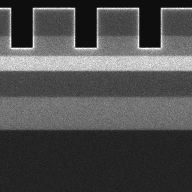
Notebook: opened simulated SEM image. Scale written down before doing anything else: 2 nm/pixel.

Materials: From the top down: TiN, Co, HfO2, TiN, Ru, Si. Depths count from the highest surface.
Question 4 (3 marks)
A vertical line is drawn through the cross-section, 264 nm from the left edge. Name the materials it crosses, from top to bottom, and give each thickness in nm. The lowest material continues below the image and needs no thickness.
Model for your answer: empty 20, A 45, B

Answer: TiN 56, Co 40, HfO2 30, TiN 52, Ru 66, Si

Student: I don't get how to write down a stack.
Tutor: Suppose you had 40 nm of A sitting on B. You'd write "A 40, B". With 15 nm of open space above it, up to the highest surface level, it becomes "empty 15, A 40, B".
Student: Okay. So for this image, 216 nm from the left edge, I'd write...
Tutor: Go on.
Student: TiN 56, Co 40, HfO2 30, TiN 52, Ru 66, Si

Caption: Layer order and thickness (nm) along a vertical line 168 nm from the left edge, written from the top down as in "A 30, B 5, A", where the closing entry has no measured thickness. empty 80, Co 16, HfO2 30, TiN 52, Ru 66, Si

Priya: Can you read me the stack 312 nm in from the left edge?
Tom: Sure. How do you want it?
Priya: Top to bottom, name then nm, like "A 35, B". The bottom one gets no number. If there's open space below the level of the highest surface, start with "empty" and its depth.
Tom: empty 80, Co 16, HfO2 30, TiN 52, Ru 66, Si